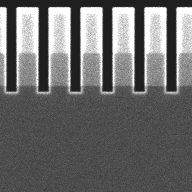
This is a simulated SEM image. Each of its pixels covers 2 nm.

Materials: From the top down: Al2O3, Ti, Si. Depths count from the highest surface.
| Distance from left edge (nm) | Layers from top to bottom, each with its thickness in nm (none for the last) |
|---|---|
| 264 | Al2O3 90, Ti 66, Si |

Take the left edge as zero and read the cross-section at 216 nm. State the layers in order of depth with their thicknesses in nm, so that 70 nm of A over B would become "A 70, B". empty 168, Si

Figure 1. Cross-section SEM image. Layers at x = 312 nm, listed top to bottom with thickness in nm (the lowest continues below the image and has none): Al2O3 90, Ti 66, Si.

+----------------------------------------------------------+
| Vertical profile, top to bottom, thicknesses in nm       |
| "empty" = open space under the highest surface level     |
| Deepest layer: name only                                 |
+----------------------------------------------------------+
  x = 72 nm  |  Al2O3 90, Ti 66, Si